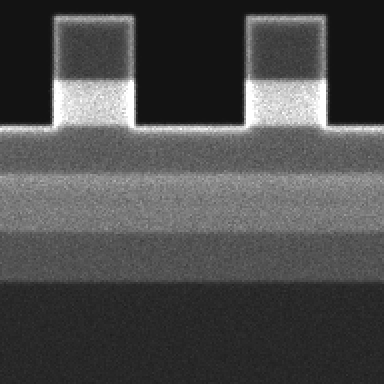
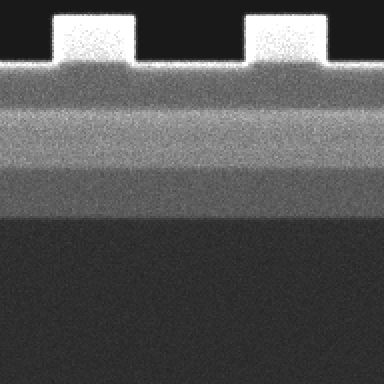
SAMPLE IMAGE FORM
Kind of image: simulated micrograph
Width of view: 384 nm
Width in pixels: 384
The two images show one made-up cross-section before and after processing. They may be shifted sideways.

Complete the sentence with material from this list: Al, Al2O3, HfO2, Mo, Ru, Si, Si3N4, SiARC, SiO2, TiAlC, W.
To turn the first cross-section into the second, SiARC must be removed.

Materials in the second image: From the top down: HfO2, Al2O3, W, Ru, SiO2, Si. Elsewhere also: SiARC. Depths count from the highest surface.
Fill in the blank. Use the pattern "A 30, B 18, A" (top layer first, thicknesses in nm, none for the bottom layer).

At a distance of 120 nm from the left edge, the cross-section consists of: HfO2 46, Al2O3 48, W 42, Ru 16, SiO2 50, Si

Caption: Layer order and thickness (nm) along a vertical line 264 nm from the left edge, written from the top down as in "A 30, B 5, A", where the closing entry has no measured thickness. HfO2 46, Al2O3 48, W 42, Ru 16, SiO2 50, Si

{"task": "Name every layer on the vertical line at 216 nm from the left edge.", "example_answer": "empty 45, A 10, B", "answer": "empty 46, Al2O3 48, W 42, Ru 16, SiO2 50, Si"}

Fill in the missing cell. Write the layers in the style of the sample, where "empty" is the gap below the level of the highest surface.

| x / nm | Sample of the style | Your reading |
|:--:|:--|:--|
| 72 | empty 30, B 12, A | HfO2 46, Al2O3 48, W 42, Ru 16, SiO2 50, Si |